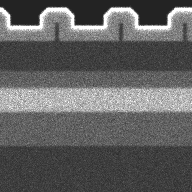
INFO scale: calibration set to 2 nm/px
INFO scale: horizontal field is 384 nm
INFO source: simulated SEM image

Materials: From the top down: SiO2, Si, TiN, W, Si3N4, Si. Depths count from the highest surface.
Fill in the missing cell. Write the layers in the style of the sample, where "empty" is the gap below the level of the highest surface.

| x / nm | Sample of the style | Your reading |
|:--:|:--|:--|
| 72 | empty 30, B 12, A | empty 36, SiO2 30, Si 60, TiN 34, W 48, Si3N4 68, Si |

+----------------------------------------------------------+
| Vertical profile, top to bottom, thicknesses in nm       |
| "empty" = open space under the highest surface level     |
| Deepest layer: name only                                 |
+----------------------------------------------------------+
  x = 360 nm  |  SiO2 66, Si 60, TiN 34, W 48, Si3N4 68, Si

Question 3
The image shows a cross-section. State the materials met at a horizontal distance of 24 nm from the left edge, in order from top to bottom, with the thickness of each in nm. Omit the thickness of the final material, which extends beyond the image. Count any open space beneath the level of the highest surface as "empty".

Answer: empty 36, SiO2 30, Si 60, TiN 34, W 48, Si3N4 68, Si